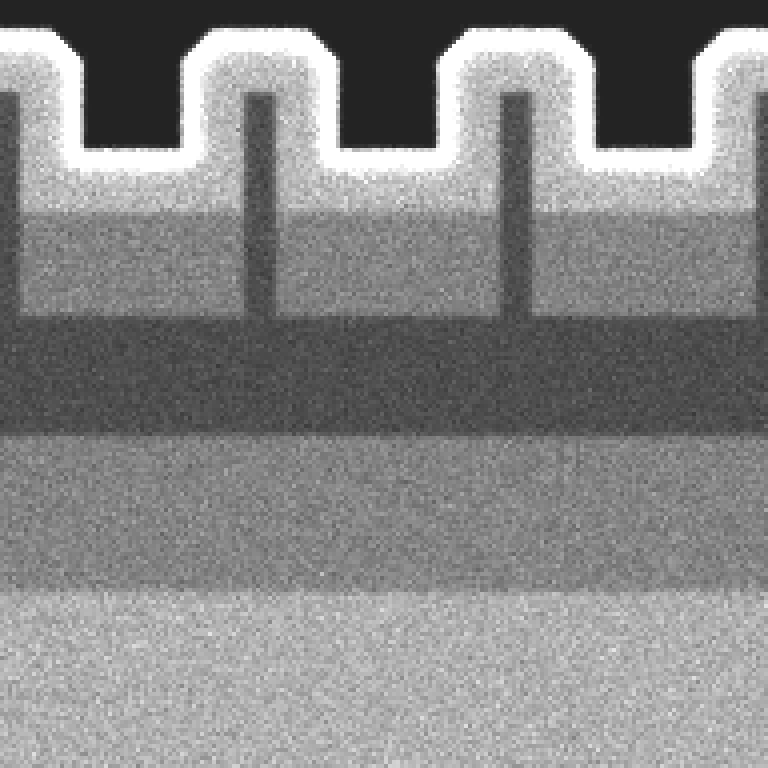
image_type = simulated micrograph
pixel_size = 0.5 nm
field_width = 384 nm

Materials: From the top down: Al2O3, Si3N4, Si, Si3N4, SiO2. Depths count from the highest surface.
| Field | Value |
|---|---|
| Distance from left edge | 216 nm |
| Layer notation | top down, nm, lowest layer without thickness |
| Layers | empty 60, Al2O3 30, Si3N4 52, Si 60, Si3N4 78, SiO2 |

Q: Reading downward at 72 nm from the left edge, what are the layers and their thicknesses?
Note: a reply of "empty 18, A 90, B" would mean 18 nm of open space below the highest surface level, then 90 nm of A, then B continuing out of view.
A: empty 60, Al2O3 30, Si3N4 52, Si 60, Si3N4 78, SiO2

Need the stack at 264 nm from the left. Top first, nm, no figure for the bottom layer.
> Al2O3 30, Si 172, Si3N4 78, SiO2